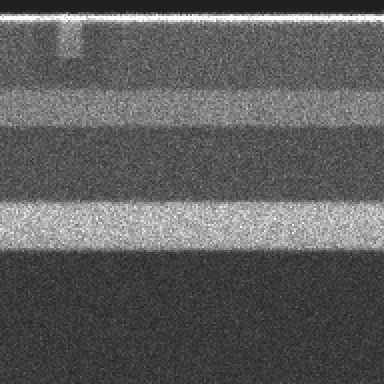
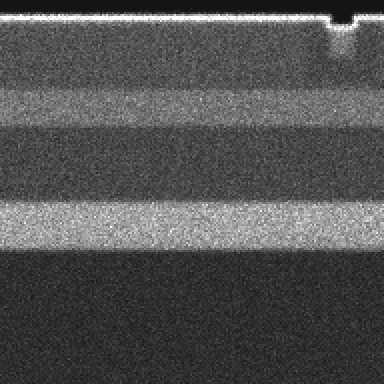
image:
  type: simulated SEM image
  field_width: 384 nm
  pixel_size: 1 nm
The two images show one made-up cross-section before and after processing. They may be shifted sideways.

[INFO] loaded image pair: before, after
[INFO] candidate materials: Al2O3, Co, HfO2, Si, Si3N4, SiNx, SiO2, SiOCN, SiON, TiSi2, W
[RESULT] removed Co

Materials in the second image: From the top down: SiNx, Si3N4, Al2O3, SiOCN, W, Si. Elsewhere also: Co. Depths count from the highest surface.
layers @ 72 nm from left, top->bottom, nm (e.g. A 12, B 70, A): Si3N4 74, Al2O3 36, SiOCN 76, W 48, Si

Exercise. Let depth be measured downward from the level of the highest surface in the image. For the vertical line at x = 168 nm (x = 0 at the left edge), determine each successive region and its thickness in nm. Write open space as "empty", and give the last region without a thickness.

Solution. Si3N4 74, Al2O3 36, SiOCN 76, W 48, Si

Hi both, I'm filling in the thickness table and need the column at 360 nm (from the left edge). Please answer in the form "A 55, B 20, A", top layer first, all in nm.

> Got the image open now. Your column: SiNx 66, Si3N4 8, Al2O3 36, SiOCN 76, W 48, Si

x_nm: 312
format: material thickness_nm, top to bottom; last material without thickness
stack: SiNx 66, Si3N4 8, Al2O3 36, SiOCN 76, W 48, Si